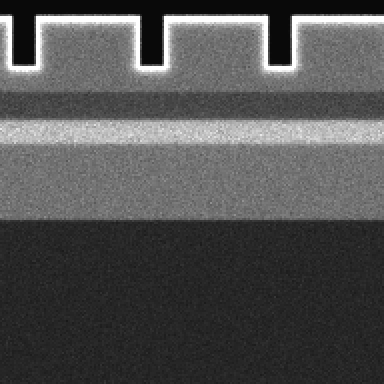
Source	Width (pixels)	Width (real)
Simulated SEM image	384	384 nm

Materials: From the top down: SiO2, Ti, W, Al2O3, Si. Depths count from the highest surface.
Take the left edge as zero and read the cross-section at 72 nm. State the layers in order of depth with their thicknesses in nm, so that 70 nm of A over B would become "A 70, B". SiO2 76, Ti 28, W 24, Al2O3 76, Si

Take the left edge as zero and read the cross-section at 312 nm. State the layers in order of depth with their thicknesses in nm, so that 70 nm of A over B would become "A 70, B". SiO2 76, Ti 28, W 24, Al2O3 76, Si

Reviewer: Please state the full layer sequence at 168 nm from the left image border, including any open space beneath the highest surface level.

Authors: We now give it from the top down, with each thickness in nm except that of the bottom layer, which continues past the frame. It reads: SiO2 76, Ti 28, W 24, Al2O3 76, Si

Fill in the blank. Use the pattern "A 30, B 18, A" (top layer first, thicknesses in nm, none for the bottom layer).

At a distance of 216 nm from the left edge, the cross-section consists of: SiO2 76, Ti 28, W 24, Al2O3 76, Si